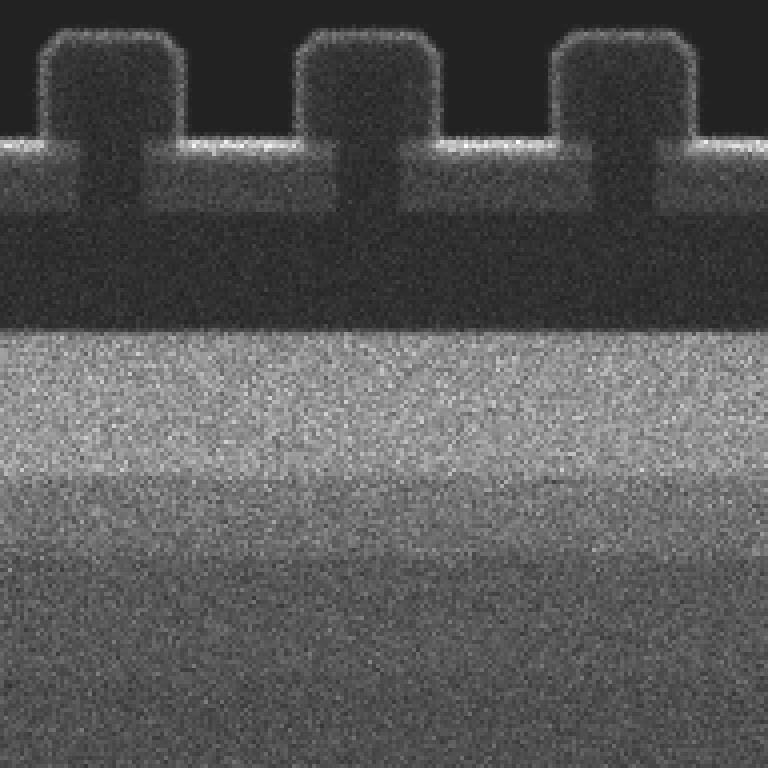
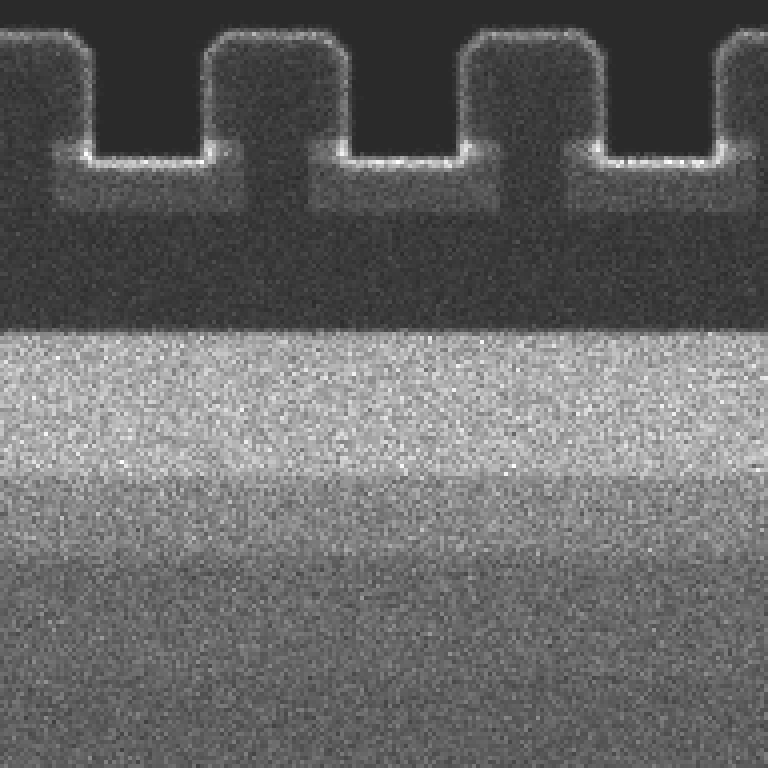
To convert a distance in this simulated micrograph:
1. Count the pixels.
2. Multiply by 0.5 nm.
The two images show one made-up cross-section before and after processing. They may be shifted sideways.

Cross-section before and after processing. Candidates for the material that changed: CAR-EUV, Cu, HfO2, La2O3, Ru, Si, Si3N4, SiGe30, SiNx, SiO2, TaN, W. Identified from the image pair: SiO2 (removed).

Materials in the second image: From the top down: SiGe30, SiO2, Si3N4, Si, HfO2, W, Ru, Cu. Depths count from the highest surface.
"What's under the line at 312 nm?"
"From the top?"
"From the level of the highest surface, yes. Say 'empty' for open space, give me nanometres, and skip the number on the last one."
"empty 64, Si3N4 26, Si 60, HfO2 72, W 40, Ru 60, Cu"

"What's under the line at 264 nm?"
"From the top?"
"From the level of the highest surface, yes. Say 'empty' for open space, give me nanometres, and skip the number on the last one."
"SiGe30 20, Si 130, HfO2 72, W 40, Ru 60, Cu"